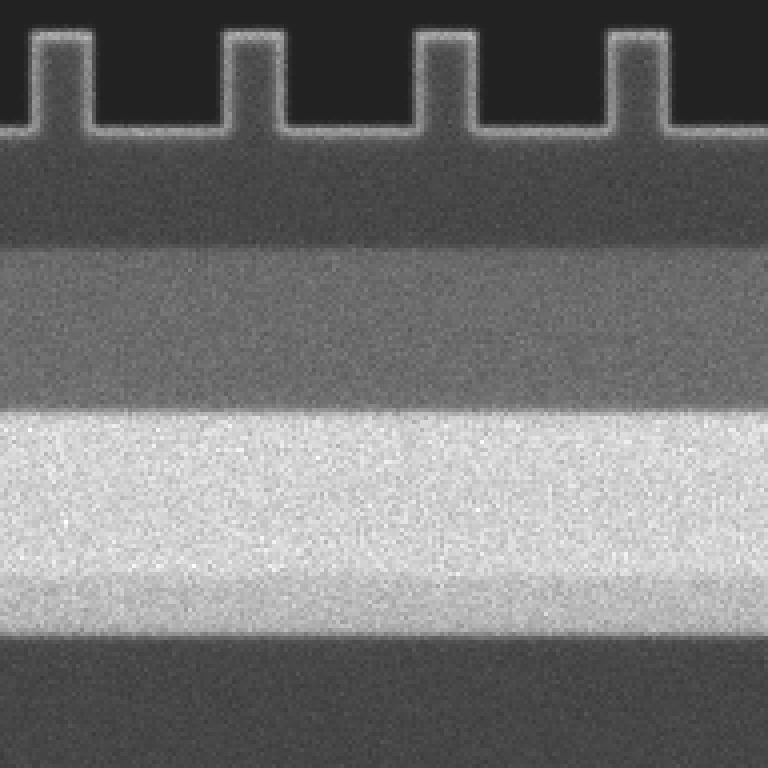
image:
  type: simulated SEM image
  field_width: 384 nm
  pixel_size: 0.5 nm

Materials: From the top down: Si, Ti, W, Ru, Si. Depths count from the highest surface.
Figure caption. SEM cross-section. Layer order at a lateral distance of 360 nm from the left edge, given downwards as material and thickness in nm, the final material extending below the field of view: empty 48, Si 60, Ti 82, W 82, Ru 30, Si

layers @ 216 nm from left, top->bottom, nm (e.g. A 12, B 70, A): Si 108, Ti 82, W 82, Ru 30, Si